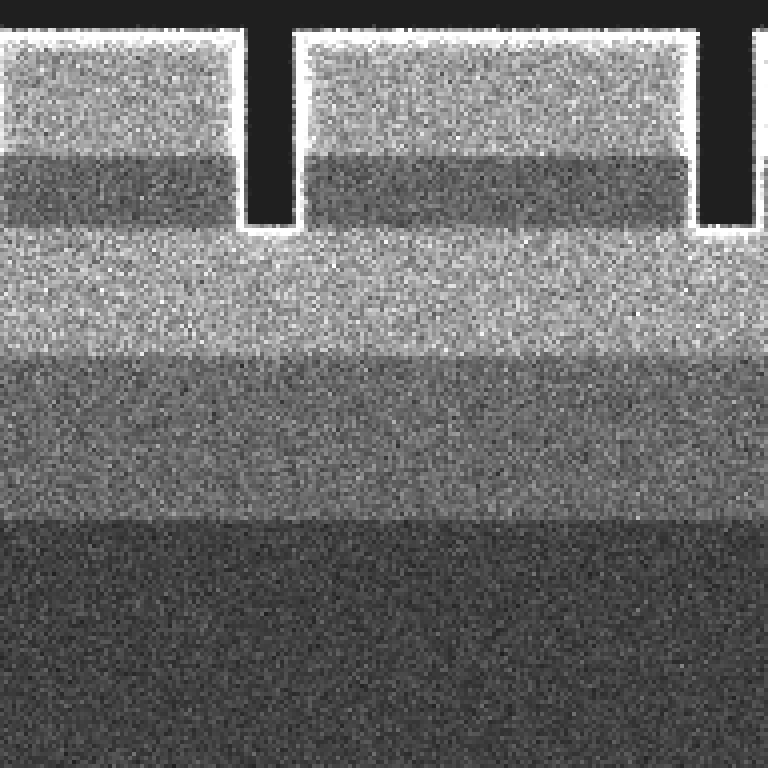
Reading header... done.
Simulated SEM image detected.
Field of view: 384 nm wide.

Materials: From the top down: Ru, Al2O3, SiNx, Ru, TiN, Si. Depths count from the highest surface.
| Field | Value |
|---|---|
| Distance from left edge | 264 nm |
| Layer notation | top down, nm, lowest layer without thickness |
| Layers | Ru 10, Al2O3 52, SiNx 36, Ru 64, TiN 82, Si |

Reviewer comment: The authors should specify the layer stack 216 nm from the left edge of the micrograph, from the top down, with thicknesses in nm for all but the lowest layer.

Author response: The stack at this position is Ru 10, Al2O3 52, SiNx 36, Ru 64, TiN 82, Si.